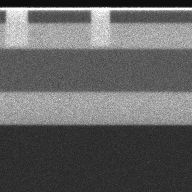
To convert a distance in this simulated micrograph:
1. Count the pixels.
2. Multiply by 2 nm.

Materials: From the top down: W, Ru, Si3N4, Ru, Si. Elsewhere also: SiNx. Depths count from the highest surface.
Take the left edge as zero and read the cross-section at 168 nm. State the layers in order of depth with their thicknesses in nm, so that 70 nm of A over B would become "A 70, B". SiNx 30, Ru 52, Si3N4 86, Ru 66, Si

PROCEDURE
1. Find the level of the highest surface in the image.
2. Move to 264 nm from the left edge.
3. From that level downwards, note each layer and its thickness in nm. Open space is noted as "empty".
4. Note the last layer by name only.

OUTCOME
SiNx 30, Ru 52, Si3N4 86, Ru 66, Si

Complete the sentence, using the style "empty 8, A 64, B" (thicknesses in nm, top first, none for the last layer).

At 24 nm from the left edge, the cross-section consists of W 76, Ru 6, Si3N4 86, Ru 66, Si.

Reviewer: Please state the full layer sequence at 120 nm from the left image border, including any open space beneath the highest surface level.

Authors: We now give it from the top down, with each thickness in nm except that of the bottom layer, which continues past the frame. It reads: SiNx 30, Ru 52, Si3N4 86, Ru 66, Si